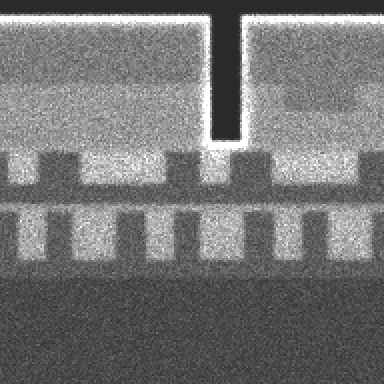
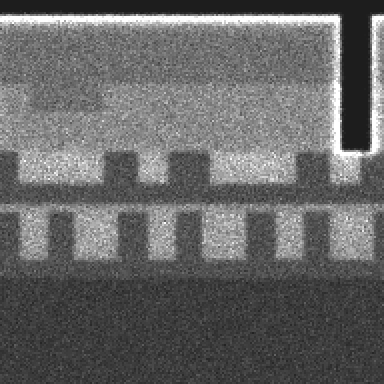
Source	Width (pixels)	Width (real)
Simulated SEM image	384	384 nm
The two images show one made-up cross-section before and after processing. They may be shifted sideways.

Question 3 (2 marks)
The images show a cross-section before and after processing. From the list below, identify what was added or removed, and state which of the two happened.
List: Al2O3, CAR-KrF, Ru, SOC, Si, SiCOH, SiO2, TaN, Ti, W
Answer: Al2O3 was removed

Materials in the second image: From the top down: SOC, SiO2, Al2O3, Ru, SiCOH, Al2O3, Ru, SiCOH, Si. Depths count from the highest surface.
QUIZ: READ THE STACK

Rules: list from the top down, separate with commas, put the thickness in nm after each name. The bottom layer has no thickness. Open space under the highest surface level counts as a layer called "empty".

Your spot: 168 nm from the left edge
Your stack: SOC 68, SiO2 58, Al2O3 10, SiCOH 52, Al2O3 8, Ru 48, SiCOH 18, Si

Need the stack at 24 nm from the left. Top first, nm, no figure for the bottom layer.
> SOC 68, SiO2 58, Al2O3 10, Ru 32, SiCOH 20, Al2O3 8, Ru 48, SiCOH 18, Si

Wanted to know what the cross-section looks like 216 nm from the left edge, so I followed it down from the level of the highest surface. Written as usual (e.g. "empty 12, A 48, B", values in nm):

SOC 68, SiO2 58, Al2O3 10, Ru 32, SiCOH 20, Al2O3 8, Ru 48, SiCOH 18, Si